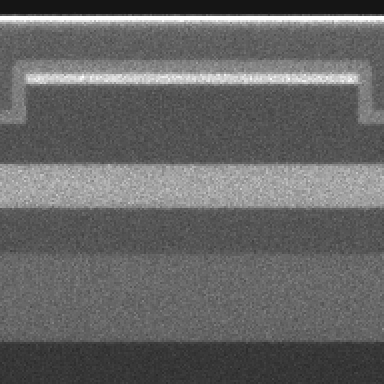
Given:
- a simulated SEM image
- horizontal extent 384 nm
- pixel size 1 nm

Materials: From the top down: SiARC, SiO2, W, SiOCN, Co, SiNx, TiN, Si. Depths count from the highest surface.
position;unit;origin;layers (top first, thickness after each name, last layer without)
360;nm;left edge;SiARC 44, SiO2 64, SiOCN 40, Co 44, SiNx 46, TiN 88, Si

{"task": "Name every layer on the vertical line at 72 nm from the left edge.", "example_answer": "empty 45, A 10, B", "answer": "SiARC 44, SiO2 14, W 10, SiOCN 80, Co 44, SiNx 46, TiN 88, Si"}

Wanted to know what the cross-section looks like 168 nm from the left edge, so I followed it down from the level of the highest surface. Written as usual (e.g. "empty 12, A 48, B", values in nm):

SiARC 44, SiO2 14, W 10, SiOCN 80, Co 44, SiNx 46, TiN 88, Si